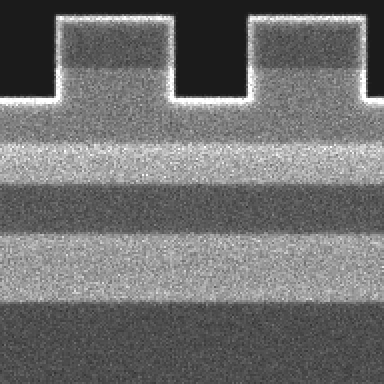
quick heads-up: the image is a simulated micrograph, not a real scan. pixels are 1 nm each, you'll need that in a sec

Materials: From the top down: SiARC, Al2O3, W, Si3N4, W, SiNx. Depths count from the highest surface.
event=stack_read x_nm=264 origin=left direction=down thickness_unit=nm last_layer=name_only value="SiARC 52, Al2O3 76, W 40, Si3N4 50, W 68, SiNx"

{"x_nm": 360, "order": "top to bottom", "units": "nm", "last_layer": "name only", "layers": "SiARC 52, Al2O3 76, W 40, Si3N4 50, W 68, SiNx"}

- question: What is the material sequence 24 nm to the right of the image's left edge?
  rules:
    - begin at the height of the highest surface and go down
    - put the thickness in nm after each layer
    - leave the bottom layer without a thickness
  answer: empty 82, Al2O3 46, W 40, Si3N4 50, W 68, SiNx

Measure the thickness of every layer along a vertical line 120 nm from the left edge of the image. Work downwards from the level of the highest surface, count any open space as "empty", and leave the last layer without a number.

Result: SiARC 52, Al2O3 76, W 40, Si3N4 50, W 68, SiNx